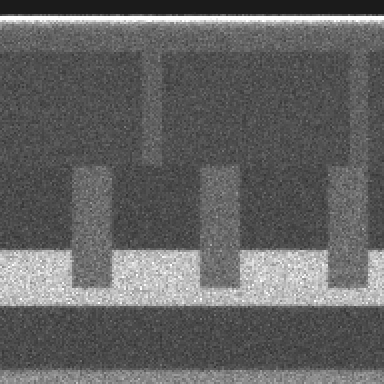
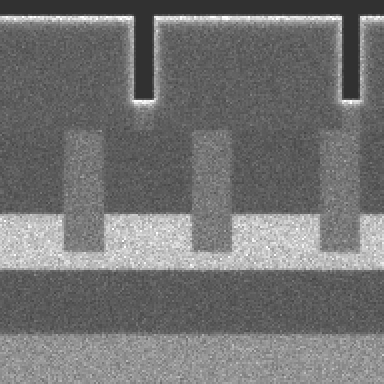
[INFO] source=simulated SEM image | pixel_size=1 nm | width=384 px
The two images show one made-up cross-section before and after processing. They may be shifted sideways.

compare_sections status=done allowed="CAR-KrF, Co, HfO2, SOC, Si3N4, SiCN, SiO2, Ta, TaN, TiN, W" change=removed material="SiO2"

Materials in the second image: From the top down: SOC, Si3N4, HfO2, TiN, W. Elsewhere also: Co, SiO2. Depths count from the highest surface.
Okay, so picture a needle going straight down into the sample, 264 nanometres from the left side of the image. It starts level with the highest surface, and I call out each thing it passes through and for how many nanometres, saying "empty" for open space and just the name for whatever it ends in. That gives SOC 114, Si3N4 84, HfO2 56, TiN 64, W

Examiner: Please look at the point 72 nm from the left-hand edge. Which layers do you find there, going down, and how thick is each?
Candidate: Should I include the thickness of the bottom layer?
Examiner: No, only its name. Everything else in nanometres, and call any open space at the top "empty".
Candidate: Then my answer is SOC 114, Co 122, HfO2 18, TiN 64, W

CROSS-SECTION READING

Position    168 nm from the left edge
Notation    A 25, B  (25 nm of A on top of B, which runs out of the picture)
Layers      SOC 114, Si3N4 84, HfO2 56, TiN 64, W